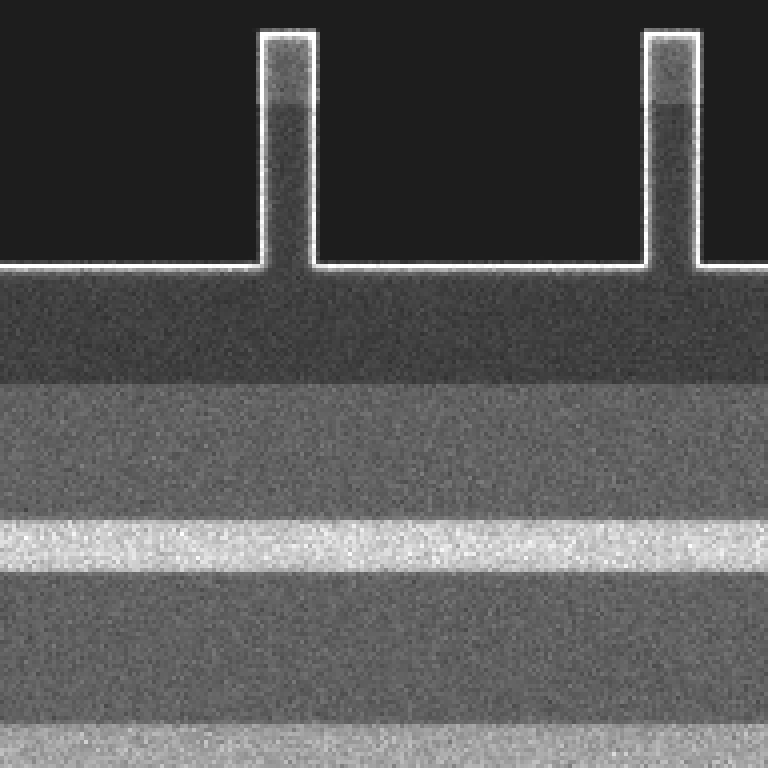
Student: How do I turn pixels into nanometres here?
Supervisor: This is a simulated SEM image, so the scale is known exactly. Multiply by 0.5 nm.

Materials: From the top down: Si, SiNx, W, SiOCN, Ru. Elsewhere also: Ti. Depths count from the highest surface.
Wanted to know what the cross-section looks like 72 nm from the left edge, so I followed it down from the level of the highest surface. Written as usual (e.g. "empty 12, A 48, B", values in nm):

empty 116, Si 60, SiNx 68, W 26, SiOCN 76, Ru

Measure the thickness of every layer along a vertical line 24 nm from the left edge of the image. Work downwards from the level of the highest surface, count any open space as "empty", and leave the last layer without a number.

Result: empty 116, Si 60, SiNx 68, W 26, SiOCN 76, Ru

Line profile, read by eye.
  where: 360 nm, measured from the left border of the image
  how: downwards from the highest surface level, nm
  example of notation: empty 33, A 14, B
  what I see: empty 116, Si 60, SiNx 68, W 26, SiOCN 76, Ru